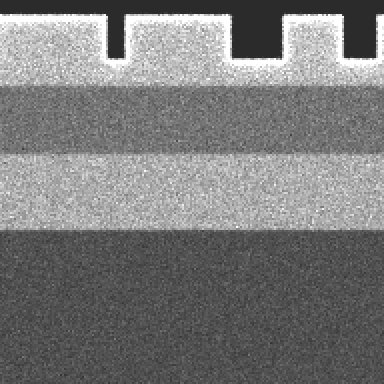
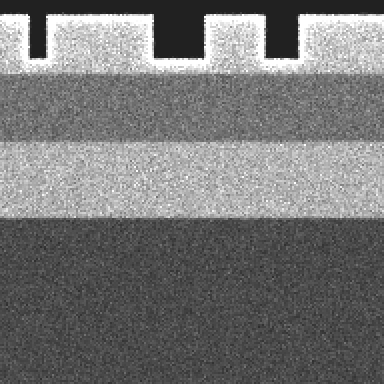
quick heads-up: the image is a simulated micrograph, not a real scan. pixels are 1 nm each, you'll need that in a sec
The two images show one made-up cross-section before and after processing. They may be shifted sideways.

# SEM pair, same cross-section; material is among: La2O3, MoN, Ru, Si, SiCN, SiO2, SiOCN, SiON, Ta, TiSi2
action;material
removed;Ru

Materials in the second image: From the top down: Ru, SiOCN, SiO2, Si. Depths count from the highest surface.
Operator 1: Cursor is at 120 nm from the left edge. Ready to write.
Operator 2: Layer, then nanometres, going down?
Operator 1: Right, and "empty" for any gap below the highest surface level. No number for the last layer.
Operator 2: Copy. Ru 58, SiOCN 68, SiO2 76, Si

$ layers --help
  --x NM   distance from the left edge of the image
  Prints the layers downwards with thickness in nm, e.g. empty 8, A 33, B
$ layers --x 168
empty 44, Ru 14, SiOCN 68, SiO2 76, Si